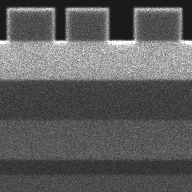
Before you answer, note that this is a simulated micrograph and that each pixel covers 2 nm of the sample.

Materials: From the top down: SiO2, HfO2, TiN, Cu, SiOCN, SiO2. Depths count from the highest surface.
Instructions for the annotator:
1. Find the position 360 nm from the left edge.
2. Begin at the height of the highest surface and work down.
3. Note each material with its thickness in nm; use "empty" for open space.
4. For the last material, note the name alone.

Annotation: SiO2 66, HfO2 78, TiN 80, Cu 80, SiOCN 30, SiO2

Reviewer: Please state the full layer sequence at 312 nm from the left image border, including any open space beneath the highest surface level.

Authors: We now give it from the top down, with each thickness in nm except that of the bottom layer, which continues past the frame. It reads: SiO2 66, HfO2 78, TiN 80, Cu 80, SiOCN 30, SiO2